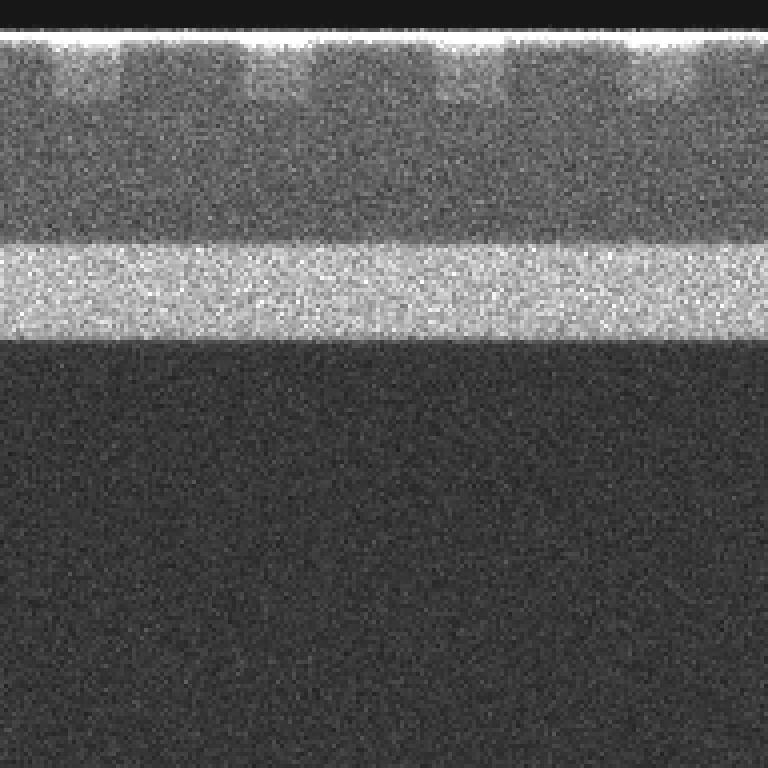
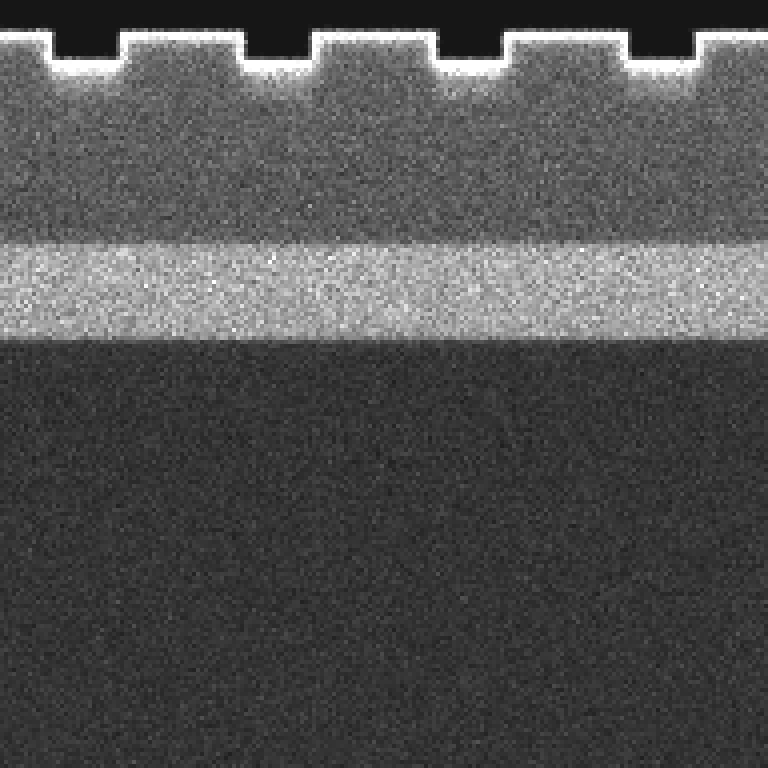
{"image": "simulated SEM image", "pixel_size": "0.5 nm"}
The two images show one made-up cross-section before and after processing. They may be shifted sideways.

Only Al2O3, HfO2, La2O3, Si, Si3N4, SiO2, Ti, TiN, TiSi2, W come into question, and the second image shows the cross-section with SiO2 removed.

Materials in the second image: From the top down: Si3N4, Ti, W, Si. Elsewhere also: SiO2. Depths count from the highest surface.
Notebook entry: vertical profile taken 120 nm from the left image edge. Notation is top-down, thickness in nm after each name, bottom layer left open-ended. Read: Si3N4 60, Ti 46, W 48, Si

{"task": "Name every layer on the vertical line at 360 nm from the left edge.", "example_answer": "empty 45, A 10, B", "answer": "Si3N4 60, Ti 46, W 48, Si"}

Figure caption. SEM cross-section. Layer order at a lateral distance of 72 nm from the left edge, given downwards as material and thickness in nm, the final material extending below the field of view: Si3N4 60, Ti 46, W 48, Si